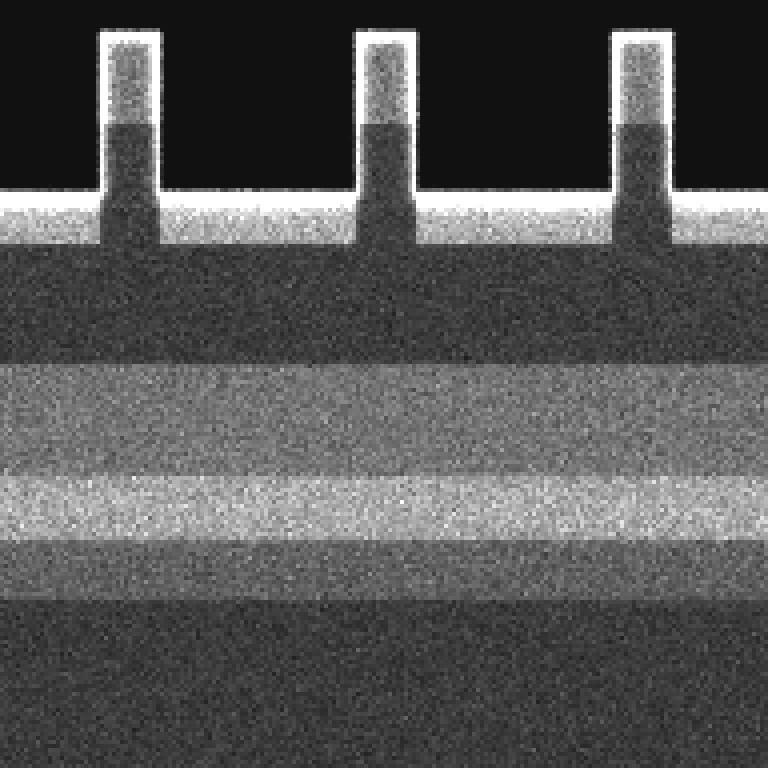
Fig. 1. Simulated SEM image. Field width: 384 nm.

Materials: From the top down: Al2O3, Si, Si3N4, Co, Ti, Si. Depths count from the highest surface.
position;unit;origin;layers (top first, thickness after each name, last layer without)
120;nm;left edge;empty 80, Al2O3 26, Si 60, Si3N4 56, Co 32, Ti 30, Si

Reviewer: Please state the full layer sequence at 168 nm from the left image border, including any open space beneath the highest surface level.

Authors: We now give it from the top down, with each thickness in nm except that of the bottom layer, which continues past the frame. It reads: empty 80, Al2O3 26, Si 60, Si3N4 56, Co 32, Ti 30, Si